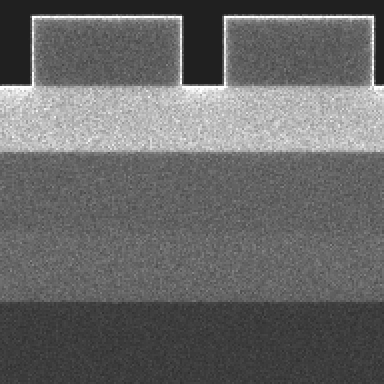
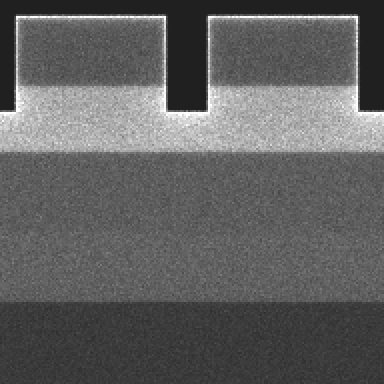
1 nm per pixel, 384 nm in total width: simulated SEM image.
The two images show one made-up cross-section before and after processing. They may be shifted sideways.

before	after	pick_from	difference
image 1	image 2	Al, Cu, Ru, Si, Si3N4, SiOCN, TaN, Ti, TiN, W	W removed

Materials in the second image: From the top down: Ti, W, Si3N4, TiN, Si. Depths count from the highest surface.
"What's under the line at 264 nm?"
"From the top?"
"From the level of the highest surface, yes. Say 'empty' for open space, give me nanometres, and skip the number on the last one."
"Ti 70, W 66, Si3N4 80, TiN 70, Si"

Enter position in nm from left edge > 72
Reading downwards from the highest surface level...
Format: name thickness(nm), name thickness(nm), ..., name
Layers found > Ti 70, W 66, Si3N4 80, TiN 70, Si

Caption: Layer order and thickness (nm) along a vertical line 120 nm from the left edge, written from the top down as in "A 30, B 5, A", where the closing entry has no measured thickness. Ti 70, W 66, Si3N4 80, TiN 70, Si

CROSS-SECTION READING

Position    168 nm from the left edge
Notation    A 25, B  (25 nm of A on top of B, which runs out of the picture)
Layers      empty 96, W 40, Si3N4 80, TiN 70, Si